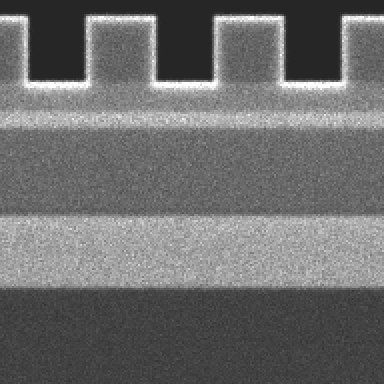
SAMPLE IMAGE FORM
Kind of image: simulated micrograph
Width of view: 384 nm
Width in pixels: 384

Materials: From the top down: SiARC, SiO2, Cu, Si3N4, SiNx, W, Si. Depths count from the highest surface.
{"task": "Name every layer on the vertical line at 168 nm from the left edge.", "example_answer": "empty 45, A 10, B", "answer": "empty 66, SiO2 30, Cu 16, Si3N4 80, SiNx 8, W 72, Si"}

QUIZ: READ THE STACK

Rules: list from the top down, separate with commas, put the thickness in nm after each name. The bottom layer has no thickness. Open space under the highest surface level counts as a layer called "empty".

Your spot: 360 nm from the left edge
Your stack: SiARC 66, SiO2 30, Cu 16, Si3N4 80, SiNx 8, W 72, Si